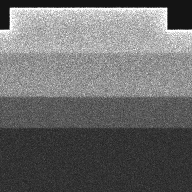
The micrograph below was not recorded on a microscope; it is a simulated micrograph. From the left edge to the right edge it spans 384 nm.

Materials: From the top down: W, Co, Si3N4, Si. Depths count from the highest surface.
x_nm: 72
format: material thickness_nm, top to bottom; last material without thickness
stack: W 90, Co 88, Si3N4 62, Si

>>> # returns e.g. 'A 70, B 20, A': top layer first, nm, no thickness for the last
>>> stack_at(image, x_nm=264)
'W 90, Co 88, Si3N4 62, Si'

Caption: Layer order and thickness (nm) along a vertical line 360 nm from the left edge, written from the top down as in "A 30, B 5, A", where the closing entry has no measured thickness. empty 44, W 46, Co 88, Si3N4 62, Si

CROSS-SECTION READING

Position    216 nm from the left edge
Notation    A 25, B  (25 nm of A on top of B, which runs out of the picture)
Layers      W 90, Co 88, Si3N4 62, Si